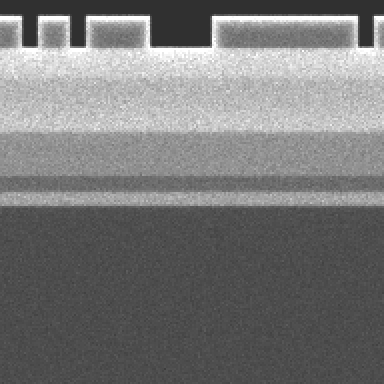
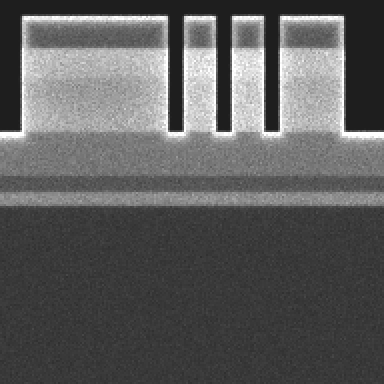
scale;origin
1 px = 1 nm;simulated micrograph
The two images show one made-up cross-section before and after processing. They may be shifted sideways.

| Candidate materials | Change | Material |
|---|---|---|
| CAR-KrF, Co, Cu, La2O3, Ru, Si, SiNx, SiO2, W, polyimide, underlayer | removed | Ru and W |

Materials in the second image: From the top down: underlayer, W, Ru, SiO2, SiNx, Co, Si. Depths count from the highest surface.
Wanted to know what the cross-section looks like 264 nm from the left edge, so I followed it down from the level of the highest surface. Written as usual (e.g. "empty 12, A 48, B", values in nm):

empty 116, SiO2 44, SiNx 16, Co 14, Si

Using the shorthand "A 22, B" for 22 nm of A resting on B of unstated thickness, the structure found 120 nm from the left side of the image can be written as underlayer 32, W 30, Ru 54, SiO2 44, SiNx 16, Co 14, Si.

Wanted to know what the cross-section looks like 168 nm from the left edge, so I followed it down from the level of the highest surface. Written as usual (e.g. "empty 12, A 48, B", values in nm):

empty 116, SiO2 44, SiNx 16, Co 14, Si